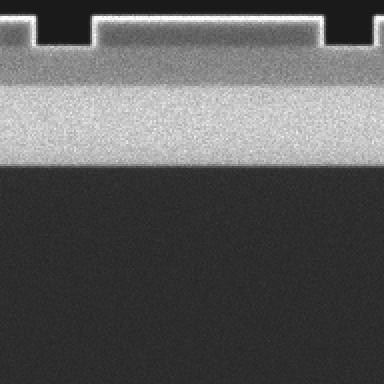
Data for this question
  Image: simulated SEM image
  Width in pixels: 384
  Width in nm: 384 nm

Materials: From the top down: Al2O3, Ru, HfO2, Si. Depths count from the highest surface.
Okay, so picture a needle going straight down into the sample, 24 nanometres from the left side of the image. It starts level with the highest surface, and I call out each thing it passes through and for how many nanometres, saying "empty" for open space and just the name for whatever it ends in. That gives Al2O3 30, Ru 40, HfO2 80, Si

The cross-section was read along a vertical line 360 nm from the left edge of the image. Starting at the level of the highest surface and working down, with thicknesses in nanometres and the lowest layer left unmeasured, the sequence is empty 30, Ru 40, HfO2 80, Si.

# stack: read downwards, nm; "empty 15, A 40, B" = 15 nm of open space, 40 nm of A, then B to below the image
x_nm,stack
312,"Al2O3 30, Ru 40, HfO2 80, Si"